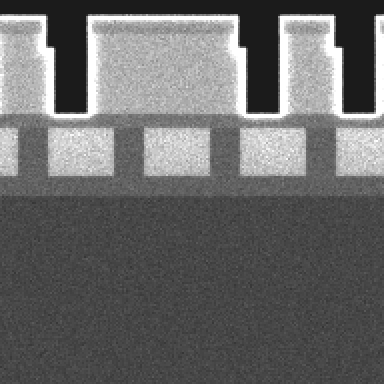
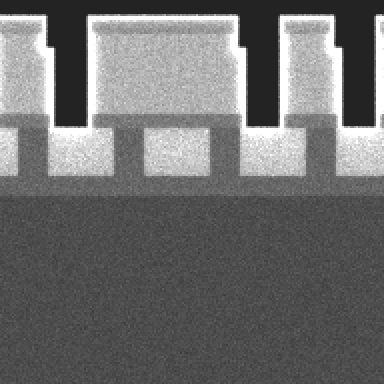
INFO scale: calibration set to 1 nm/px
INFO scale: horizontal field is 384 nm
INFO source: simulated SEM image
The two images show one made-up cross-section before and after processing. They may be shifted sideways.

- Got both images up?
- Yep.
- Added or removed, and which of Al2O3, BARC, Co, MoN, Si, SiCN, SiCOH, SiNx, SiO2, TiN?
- removed, SiNx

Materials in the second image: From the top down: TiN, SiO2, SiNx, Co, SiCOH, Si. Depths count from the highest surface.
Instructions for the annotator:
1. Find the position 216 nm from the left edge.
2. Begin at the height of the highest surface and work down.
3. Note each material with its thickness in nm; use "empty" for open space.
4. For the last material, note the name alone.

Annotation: TiN 18, SiO2 80, SiNx 14, SiCOH 68, Si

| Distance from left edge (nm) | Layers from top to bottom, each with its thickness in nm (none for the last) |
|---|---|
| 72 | empty 112, Co 48, SiCOH 20, Si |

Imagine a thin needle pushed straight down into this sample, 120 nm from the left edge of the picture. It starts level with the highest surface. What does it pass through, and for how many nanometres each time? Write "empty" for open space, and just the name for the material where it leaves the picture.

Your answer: TiN 18, SiO2 80, SiNx 14, SiCOH 68, Si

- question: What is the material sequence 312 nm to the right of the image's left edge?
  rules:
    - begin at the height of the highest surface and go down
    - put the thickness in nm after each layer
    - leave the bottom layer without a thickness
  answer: TiN 18, SiO2 80, SiNx 14, SiCOH 68, Si